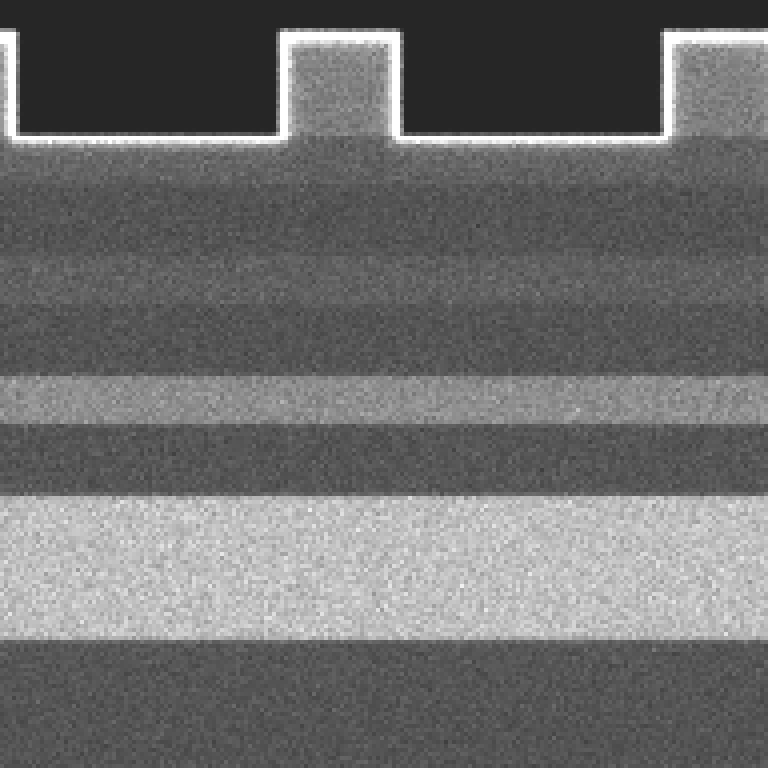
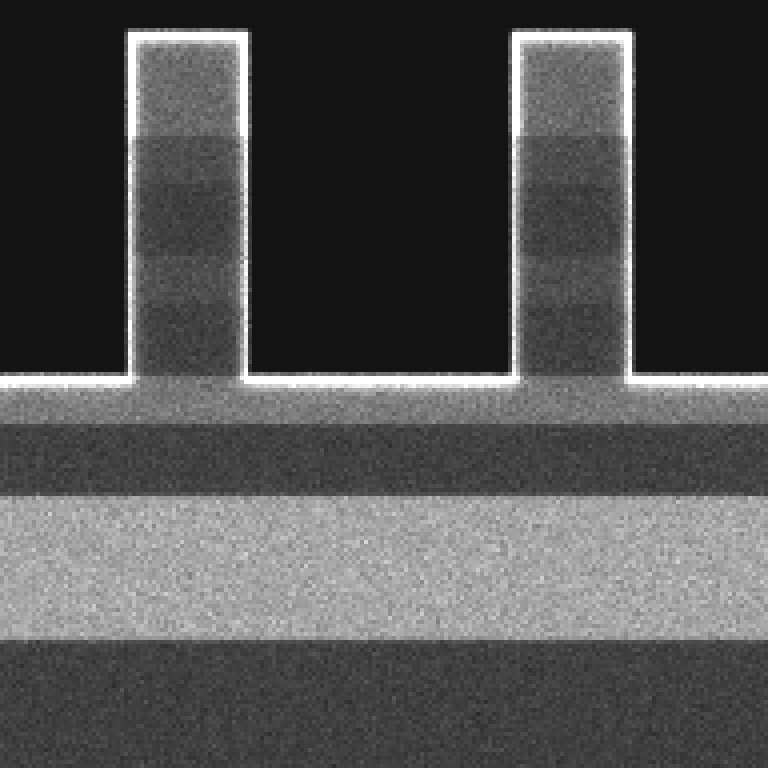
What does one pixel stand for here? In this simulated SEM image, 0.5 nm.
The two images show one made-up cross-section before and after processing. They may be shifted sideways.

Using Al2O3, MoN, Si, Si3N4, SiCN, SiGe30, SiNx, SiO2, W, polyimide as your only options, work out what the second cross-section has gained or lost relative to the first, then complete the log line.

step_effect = removed Si and SiGe30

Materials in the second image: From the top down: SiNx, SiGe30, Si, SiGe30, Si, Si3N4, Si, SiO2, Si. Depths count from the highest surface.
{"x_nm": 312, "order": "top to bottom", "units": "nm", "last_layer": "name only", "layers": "SiNx 52, SiGe30 24, Si 36, SiGe30 24, Si 36, Si3N4 24, Si 36, SiO2 72, Si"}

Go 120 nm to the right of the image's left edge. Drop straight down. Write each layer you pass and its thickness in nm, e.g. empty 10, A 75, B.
SiNx 52, SiGe30 24, Si 36, SiGe30 24, Si 36, Si3N4 24, Si 36, SiO2 72, Si